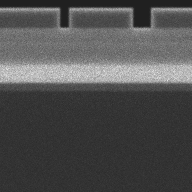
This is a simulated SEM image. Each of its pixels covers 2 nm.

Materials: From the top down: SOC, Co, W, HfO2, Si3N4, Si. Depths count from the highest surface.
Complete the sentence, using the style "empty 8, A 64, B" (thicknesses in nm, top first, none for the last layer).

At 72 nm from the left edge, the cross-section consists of SOC 40, Co 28, W 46, HfO2 36, Si3N4 16, Si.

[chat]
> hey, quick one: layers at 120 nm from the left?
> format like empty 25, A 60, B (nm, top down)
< empty 40, Co 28, W 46, HfO2 36, Si3N4 16, Si